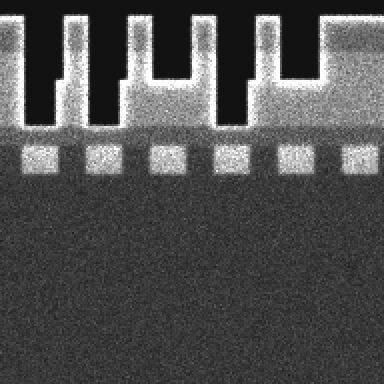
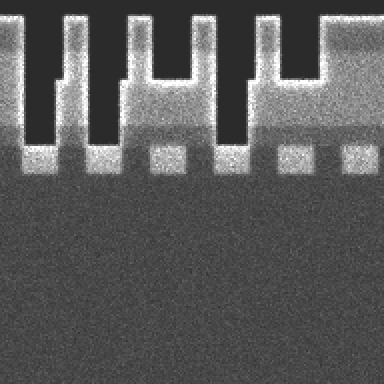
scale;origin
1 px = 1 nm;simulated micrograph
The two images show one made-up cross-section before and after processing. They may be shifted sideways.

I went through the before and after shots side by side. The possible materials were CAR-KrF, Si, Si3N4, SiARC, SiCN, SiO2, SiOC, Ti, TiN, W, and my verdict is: removed, SiCN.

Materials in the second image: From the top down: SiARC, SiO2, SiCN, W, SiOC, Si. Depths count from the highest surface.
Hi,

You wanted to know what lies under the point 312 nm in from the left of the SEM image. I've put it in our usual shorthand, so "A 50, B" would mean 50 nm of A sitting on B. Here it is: empty 64, SiO2 46, SiCN 20, W 28, SiOC 38, Si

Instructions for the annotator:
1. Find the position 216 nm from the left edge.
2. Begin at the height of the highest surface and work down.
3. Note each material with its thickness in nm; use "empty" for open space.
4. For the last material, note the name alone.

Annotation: empty 130, W 28, SiOC 38, Si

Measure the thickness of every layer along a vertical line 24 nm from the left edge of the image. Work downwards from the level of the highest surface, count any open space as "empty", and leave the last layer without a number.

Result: empty 130, W 28, SiOC 38, Si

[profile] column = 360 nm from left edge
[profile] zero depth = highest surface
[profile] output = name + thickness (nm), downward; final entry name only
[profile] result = SiARC 36, SiO2 74, SiCN 20, W 28, SiOC 38, Si